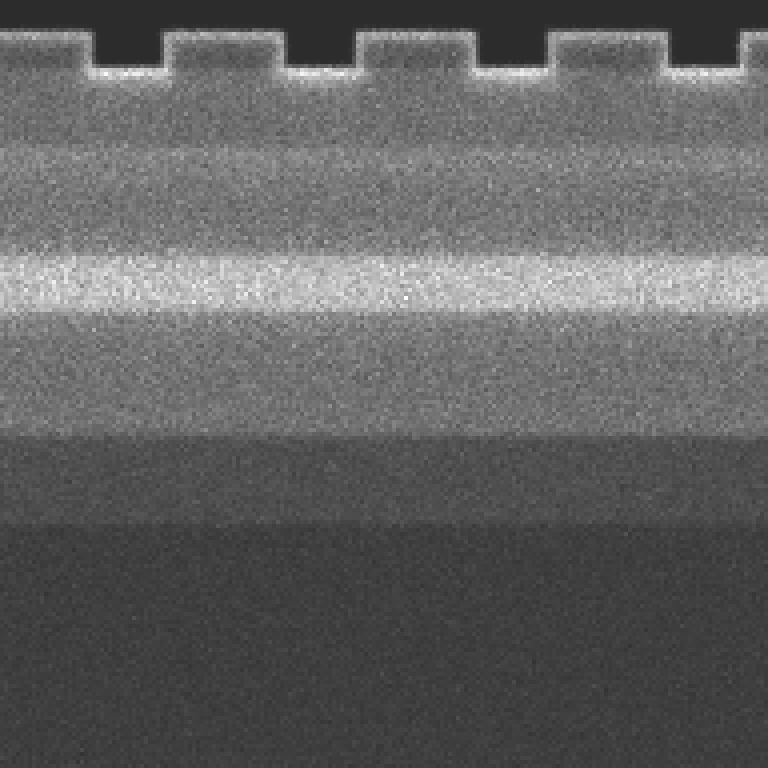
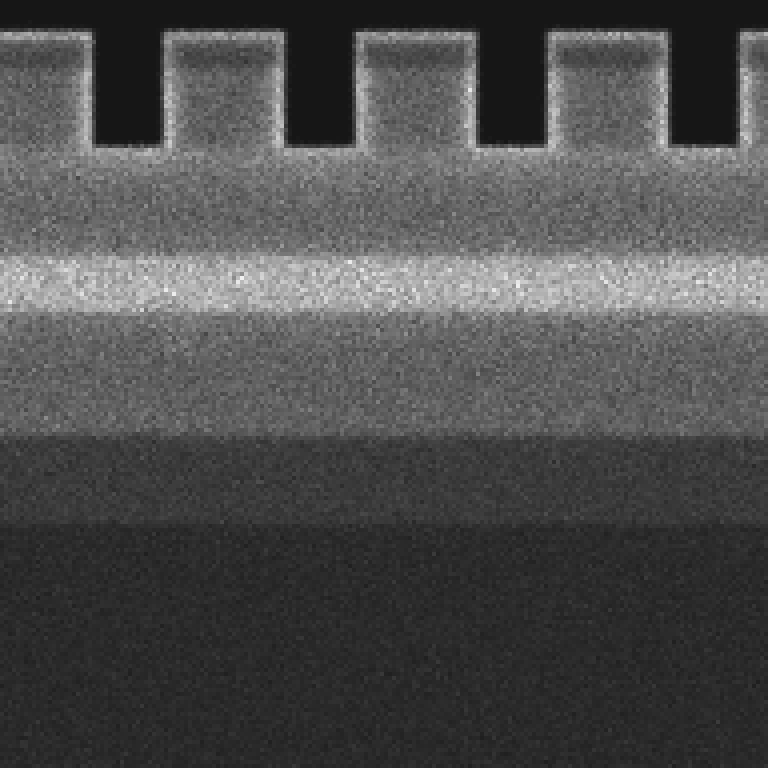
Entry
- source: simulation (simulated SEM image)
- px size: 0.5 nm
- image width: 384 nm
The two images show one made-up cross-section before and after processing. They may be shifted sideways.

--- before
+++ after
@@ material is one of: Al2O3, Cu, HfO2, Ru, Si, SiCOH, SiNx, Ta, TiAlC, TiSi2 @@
Al2O3 removed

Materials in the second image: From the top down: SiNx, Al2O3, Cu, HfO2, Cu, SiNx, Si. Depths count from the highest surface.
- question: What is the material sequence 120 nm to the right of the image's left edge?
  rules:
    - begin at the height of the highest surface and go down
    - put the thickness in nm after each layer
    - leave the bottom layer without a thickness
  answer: SiNx 18, Al2O3 40, Cu 54, HfO2 28, Cu 62, SiNx 44, Si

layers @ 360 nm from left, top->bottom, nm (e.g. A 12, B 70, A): empty 58, Cu 54, HfO2 28, Cu 62, SiNx 44, Si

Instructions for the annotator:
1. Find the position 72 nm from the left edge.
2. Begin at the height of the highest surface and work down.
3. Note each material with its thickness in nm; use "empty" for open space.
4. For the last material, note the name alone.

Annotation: empty 58, Cu 54, HfO2 28, Cu 62, SiNx 44, Si